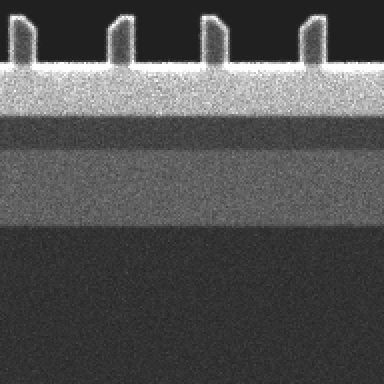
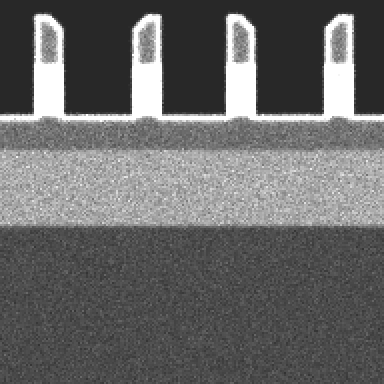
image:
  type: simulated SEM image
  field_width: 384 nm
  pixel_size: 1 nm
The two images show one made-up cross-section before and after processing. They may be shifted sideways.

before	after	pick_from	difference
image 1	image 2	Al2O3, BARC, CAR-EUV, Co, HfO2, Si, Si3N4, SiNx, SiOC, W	HfO2 removed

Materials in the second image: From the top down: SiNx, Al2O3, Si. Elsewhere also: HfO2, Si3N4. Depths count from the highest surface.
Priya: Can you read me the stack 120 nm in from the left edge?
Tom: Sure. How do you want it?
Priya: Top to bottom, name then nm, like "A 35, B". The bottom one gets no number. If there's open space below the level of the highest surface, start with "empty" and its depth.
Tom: empty 100, SiNx 34, Al2O3 76, Si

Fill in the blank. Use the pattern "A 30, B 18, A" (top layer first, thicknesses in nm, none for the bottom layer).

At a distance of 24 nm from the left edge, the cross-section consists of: empty 100, SiNx 34, Al2O3 76, Si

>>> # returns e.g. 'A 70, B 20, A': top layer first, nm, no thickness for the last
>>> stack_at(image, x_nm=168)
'empty 100, SiNx 34, Al2O3 76, Si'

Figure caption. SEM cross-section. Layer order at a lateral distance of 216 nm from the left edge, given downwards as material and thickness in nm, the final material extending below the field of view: empty 100, SiNx 34, Al2O3 76, Si